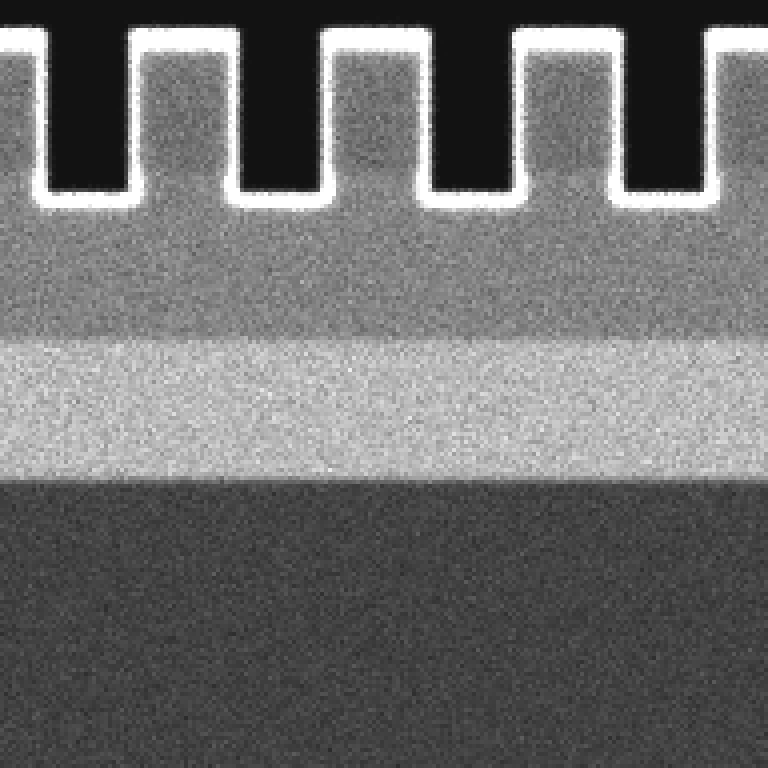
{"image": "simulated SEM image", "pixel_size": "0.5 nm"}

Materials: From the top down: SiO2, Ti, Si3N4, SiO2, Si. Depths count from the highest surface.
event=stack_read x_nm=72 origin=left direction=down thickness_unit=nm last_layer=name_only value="SiO2 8, Ti 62, Si3N4 84, SiO2 70, Si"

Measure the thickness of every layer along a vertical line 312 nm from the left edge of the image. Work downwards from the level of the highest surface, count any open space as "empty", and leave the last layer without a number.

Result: empty 82, Si3N4 72, SiO2 70, Si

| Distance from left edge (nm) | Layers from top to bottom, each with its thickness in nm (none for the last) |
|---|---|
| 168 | SiO2 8, Ti 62, Si3N4 84, SiO2 70, Si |